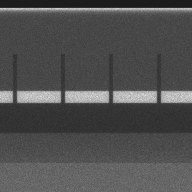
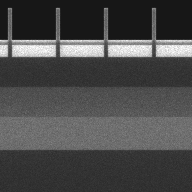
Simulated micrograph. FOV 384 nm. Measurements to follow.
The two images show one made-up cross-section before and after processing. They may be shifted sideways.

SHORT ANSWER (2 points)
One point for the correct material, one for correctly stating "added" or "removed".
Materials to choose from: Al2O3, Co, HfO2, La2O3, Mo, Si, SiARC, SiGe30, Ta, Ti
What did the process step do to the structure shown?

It removed SiARC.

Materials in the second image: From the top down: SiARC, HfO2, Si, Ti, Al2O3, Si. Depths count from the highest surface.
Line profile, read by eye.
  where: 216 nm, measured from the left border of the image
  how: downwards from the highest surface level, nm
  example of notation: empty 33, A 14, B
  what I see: empty 64, SiARC 10, HfO2 24, Si 60, Ti 60, Al2O3 66, Si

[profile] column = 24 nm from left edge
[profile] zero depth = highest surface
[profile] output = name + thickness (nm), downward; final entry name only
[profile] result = empty 64, SiARC 10, HfO2 24, Si 60, Ti 60, Al2O3 66, Si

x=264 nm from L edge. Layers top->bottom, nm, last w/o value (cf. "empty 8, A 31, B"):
empty 64, SiARC 10, HfO2 24, Si 60, Ti 60, Al2O3 66, Si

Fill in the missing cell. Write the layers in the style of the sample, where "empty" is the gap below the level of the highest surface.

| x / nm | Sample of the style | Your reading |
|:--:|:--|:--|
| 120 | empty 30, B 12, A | empty 64, SiARC 10, HfO2 24, Si 60, Ti 60, Al2O3 66, Si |